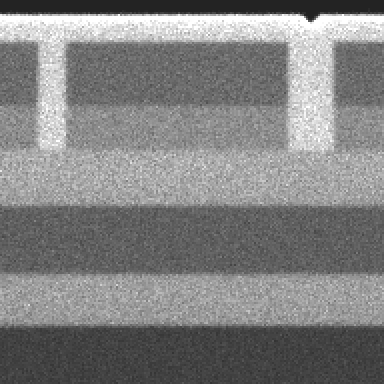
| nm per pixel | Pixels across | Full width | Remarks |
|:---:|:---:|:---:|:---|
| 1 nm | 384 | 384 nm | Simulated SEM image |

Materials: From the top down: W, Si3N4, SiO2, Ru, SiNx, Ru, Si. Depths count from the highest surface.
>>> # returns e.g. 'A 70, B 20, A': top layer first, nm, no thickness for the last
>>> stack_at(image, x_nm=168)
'W 26, Si3N4 64, SiO2 44, Ru 56, SiNx 68, Ru 52, Si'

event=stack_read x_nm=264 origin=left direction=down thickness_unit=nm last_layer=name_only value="W 26, Si3N4 64, SiO2 44, Ru 56, SiNx 68, Ru 52, Si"